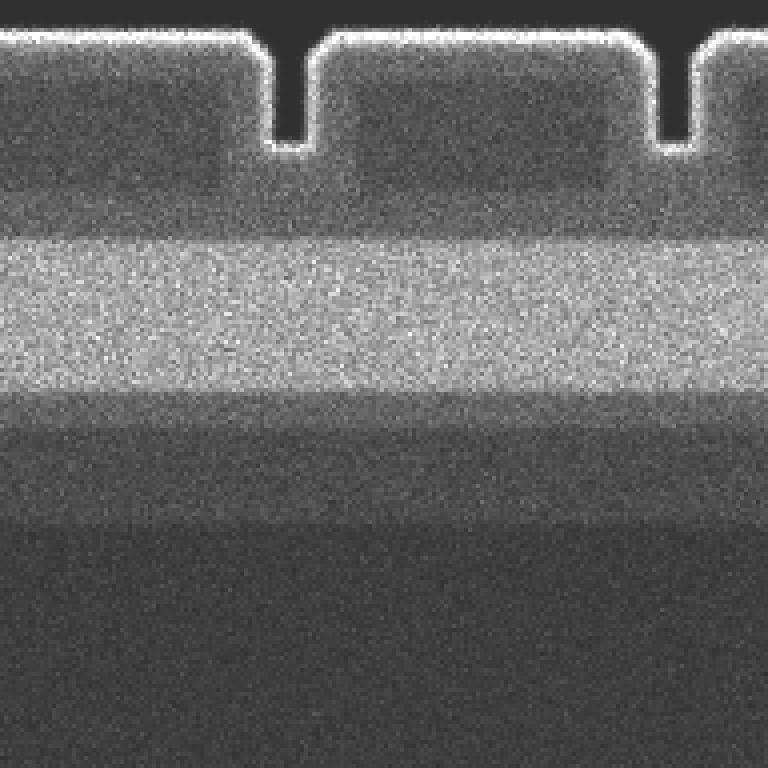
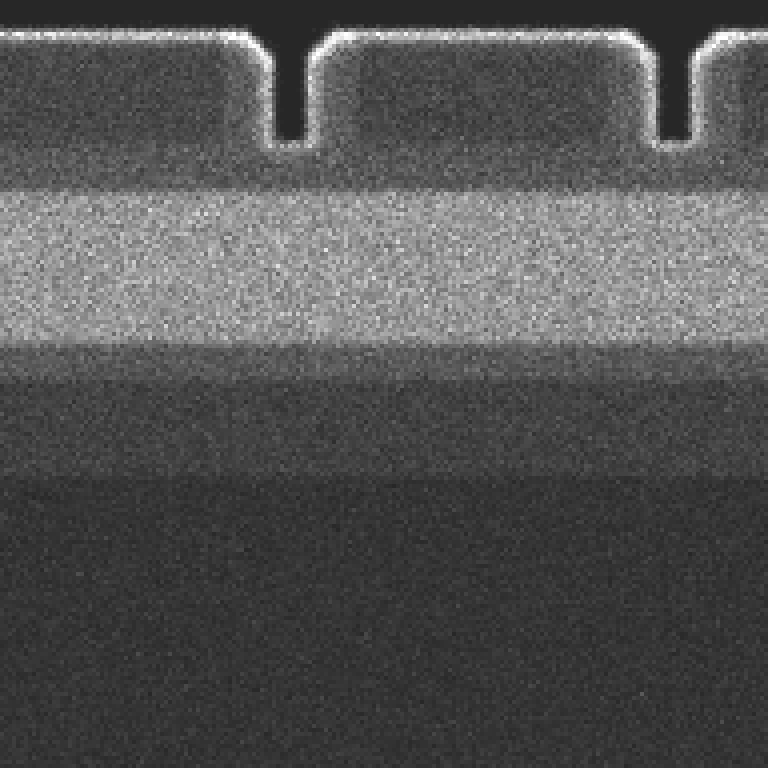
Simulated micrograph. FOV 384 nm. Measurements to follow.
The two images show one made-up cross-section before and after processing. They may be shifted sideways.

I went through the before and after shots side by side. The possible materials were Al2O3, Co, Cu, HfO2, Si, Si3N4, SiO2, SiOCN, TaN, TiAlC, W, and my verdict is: removed, Al2O3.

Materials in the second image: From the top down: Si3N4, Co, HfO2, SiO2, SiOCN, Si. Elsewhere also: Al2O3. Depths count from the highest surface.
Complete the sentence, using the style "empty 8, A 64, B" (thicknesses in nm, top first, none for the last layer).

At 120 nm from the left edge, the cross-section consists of Al2O3 56, Co 24, HfO2 76, SiO2 18, SiOCN 48, Si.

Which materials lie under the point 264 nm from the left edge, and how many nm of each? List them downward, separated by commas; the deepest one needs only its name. Si3N4 56, Co 24, HfO2 76, SiO2 18, SiOCN 48, Si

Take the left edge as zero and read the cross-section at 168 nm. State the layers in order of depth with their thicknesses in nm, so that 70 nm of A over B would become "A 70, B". Al2O3 56, Co 24, HfO2 76, SiO2 18, SiOCN 48, Si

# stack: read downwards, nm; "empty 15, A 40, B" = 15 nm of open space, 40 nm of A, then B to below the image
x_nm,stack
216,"Si3N4 56, Co 24, HfO2 76, SiO2 18, SiOCN 48, Si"